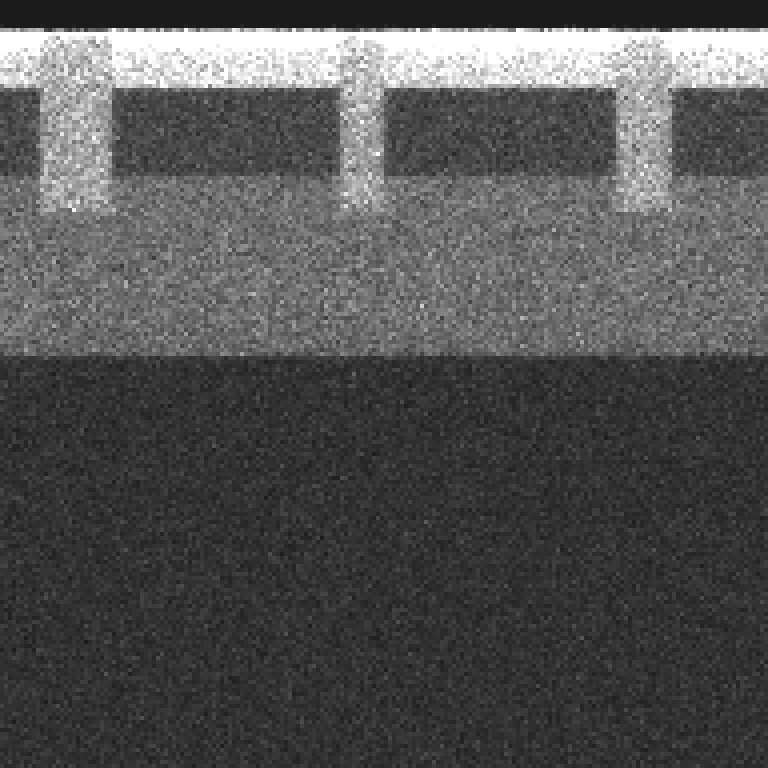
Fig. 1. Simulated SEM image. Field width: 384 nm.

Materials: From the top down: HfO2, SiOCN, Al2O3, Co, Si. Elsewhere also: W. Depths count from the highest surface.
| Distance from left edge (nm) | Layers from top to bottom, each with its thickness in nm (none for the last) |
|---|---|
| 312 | W 90, Al2O3 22, Co 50, Si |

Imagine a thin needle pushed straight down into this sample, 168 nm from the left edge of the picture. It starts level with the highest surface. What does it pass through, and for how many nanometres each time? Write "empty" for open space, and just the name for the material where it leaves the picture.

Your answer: HfO2 28, SiOCN 44, Al2O3 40, Co 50, Si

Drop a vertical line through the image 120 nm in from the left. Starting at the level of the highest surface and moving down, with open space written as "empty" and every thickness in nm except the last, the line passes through HfO2 28, SiOCN 44, Al2O3 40, Co 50, Si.